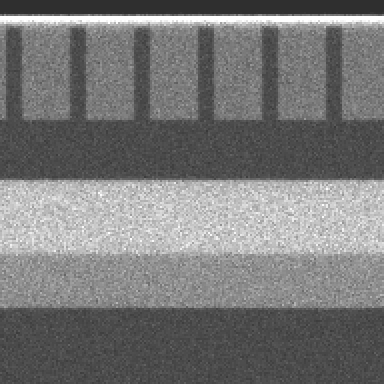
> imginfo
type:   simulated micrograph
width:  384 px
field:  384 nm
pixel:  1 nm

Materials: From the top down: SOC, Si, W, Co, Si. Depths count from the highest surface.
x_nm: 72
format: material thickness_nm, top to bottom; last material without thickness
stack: SOC 10, Si 154, W 74, Co 54, Si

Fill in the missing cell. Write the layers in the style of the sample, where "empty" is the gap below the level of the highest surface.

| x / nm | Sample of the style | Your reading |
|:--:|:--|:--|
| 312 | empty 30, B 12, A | SOC 104, Si 60, W 74, Co 54, Si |